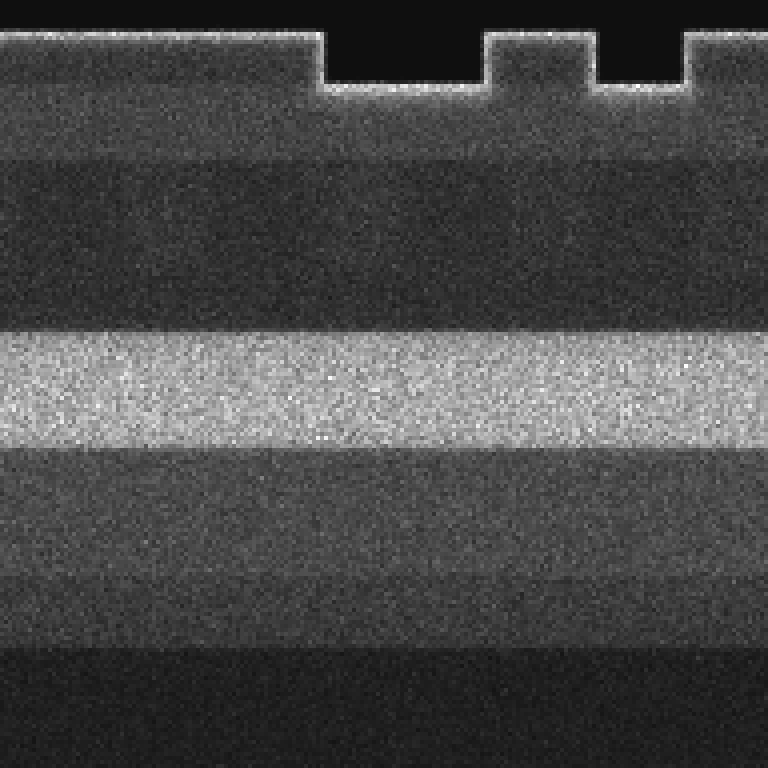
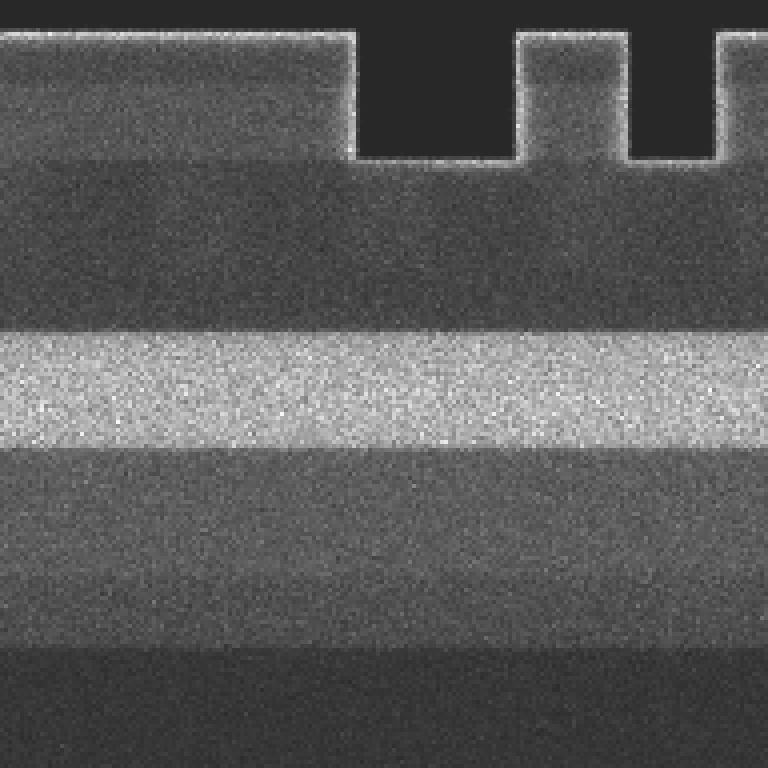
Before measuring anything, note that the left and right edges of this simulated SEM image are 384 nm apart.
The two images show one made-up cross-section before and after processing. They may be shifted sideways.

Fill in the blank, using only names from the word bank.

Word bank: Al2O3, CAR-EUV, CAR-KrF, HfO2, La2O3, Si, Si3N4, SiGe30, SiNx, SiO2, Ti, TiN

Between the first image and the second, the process removed SiO2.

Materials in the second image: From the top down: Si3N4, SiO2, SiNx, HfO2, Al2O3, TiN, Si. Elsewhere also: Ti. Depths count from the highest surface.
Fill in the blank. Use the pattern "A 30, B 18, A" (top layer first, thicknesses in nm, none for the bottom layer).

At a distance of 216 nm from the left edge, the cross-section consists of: empty 64, SiNx 86, HfO2 58, Al2O3 64, TiN 36, Si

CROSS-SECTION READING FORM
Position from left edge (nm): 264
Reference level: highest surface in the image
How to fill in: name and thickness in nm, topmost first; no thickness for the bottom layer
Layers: Si3N4 26, SiO2 38, SiNx 86, HfO2 58, Al2O3 64, TiN 36, Si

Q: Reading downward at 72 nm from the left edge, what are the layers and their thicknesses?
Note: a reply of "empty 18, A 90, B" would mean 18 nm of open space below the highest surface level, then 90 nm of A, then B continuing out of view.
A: Si3N4 26, SiO2 38, SiNx 86, HfO2 58, Al2O3 64, TiN 36, Si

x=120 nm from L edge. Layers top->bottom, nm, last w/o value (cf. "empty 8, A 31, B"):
Si3N4 26, SiO2 38, SiNx 86, HfO2 58, Al2O3 64, TiN 36, Si